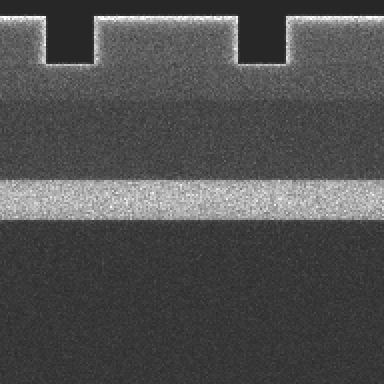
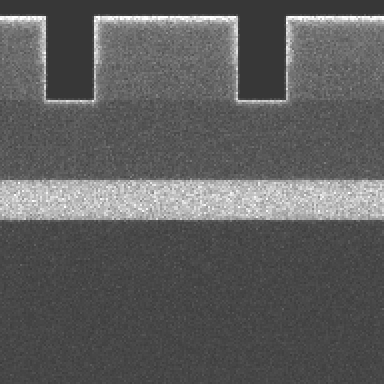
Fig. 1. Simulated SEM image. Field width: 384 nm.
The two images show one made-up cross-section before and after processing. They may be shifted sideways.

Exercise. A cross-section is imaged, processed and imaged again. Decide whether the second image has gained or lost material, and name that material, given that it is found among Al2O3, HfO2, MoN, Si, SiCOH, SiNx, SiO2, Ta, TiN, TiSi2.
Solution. removed: TiN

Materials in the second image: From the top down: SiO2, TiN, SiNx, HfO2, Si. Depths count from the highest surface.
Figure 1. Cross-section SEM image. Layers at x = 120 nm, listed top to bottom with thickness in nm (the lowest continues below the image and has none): SiO2 48, TiN 36, SiNx 80, HfO2 40, Si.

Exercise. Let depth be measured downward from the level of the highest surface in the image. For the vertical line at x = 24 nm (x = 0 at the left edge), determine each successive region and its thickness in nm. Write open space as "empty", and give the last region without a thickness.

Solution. SiO2 48, TiN 36, SiNx 80, HfO2 40, Si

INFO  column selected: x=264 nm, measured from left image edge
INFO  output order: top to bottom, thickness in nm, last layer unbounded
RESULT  empty 84, SiNx 80, HfO2 40, Si